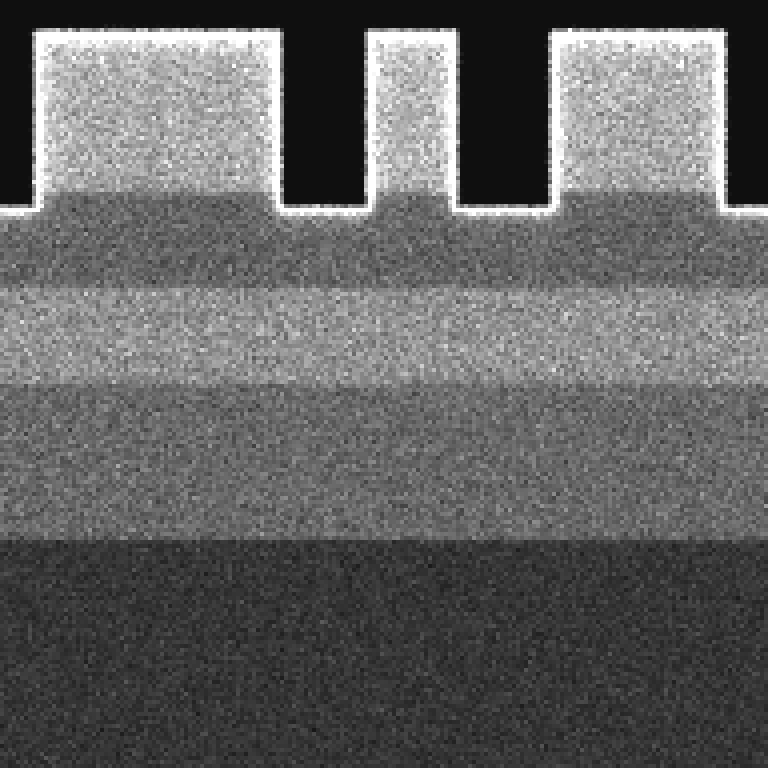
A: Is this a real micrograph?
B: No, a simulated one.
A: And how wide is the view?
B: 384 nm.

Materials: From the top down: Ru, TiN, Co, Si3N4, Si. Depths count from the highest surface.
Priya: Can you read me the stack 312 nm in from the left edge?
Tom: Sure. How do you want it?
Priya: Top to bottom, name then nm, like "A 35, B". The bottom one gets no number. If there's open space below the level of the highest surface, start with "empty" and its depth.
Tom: Ru 80, TiN 48, Co 48, Si3N4 78, Si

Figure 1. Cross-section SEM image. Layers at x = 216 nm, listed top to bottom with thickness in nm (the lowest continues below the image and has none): Ru 80, TiN 48, Co 48, Si3N4 78, Si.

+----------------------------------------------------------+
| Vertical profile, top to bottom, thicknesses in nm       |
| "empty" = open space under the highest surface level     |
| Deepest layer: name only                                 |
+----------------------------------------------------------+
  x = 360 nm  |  Ru 80, TiN 48, Co 48, Si3N4 78, Si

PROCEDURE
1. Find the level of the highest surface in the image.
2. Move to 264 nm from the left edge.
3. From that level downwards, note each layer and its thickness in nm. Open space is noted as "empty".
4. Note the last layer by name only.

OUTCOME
empty 88, TiN 40, Co 48, Si3N4 78, Si